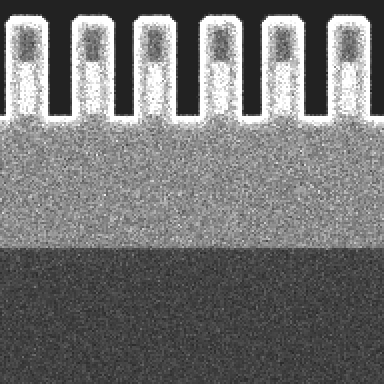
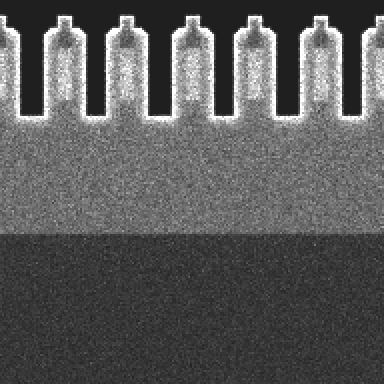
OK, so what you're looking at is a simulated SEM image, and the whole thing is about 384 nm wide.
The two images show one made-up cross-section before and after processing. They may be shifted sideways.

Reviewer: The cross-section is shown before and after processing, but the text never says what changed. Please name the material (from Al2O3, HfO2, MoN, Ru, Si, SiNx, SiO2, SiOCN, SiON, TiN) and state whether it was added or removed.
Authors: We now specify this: Al2O3, removed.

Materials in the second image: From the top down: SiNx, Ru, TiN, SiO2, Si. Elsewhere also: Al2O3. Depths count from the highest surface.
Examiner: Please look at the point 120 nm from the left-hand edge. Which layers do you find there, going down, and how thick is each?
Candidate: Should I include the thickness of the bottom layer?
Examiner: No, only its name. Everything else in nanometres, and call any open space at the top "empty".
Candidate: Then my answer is SiNx 32, Ru 52, TiN 16, SiO2 118, Si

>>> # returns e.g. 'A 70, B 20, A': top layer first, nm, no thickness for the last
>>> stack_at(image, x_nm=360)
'empty 100, SiO2 118, Si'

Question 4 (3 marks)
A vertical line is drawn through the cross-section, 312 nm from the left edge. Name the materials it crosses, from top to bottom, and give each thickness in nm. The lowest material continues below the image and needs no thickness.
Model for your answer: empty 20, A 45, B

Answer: empty 12, Al2O3 88, SiO2 118, Si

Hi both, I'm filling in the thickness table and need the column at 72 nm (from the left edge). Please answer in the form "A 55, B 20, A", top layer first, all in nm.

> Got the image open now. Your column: empty 12, Al2O3 88, SiO2 118, Si